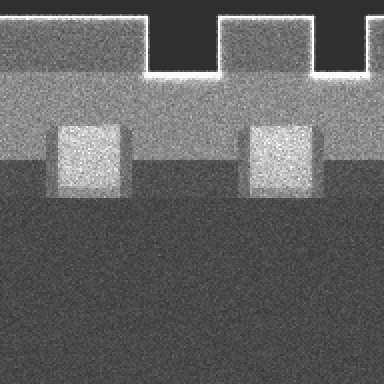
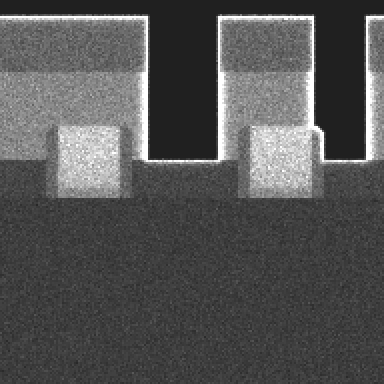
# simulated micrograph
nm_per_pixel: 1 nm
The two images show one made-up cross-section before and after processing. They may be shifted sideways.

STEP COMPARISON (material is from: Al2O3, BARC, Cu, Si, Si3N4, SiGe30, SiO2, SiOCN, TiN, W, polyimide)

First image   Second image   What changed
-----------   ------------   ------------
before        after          SiO2, removed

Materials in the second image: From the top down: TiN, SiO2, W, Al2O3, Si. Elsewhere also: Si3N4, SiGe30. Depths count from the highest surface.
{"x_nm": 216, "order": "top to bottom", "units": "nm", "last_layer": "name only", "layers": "empty 144, SiGe30 38, Si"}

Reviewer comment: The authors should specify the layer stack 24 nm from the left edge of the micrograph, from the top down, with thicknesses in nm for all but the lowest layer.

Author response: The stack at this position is TiN 56, SiO2 88, SiGe30 38, Si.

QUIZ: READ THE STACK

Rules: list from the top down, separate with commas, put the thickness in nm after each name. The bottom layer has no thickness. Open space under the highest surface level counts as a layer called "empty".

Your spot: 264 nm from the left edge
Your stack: TiN 56, SiO2 54, W 62, Al2O3 10, Si